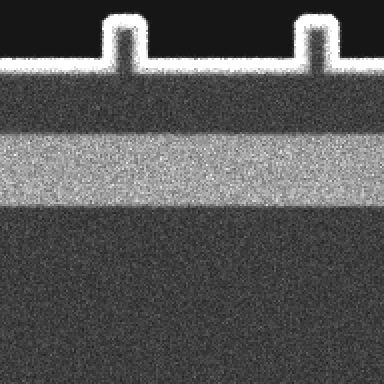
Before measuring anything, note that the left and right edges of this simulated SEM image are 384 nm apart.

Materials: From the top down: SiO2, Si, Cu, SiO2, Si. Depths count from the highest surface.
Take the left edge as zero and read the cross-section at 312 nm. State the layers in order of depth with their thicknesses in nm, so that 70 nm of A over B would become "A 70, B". SiO2 14, Si 104, Cu 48, SiO2 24, Si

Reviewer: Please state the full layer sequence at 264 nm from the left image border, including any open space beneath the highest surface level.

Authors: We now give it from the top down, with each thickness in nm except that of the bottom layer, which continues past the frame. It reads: empty 44, SiO2 14, Si 60, Cu 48, SiO2 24, Si